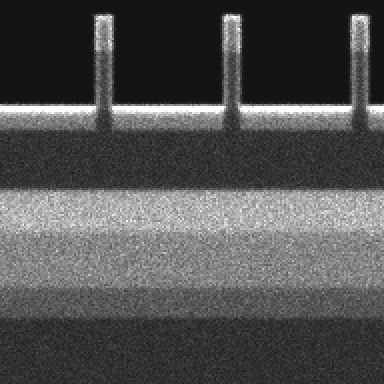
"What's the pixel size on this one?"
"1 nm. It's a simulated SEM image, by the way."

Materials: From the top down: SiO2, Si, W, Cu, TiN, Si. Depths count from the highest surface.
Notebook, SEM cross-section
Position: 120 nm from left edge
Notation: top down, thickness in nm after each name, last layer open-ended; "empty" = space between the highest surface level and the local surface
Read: empty 90, SiO2 24, Si 60, W 42, Cu 56, TiN 30, Si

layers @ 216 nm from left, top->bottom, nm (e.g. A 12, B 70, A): empty 90, SiO2 24, Si 60, W 42, Cu 56, TiN 30, Si